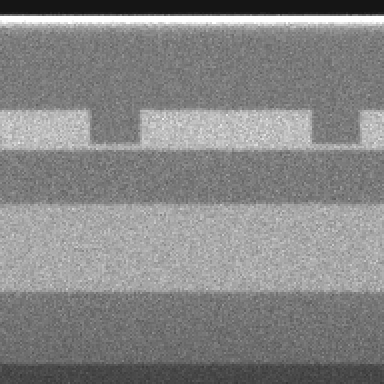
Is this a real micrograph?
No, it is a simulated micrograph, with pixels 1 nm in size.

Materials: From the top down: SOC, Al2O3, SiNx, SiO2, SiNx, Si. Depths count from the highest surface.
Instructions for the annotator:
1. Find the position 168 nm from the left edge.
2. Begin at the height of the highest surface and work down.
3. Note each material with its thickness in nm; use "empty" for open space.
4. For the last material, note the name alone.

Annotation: SOC 94, Al2O3 40, SiNx 54, SiO2 88, SiNx 72, Si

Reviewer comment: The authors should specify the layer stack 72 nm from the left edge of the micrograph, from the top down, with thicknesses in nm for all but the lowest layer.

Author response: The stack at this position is SOC 94, Al2O3 40, SiNx 54, SiO2 88, SiNx 72, Si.